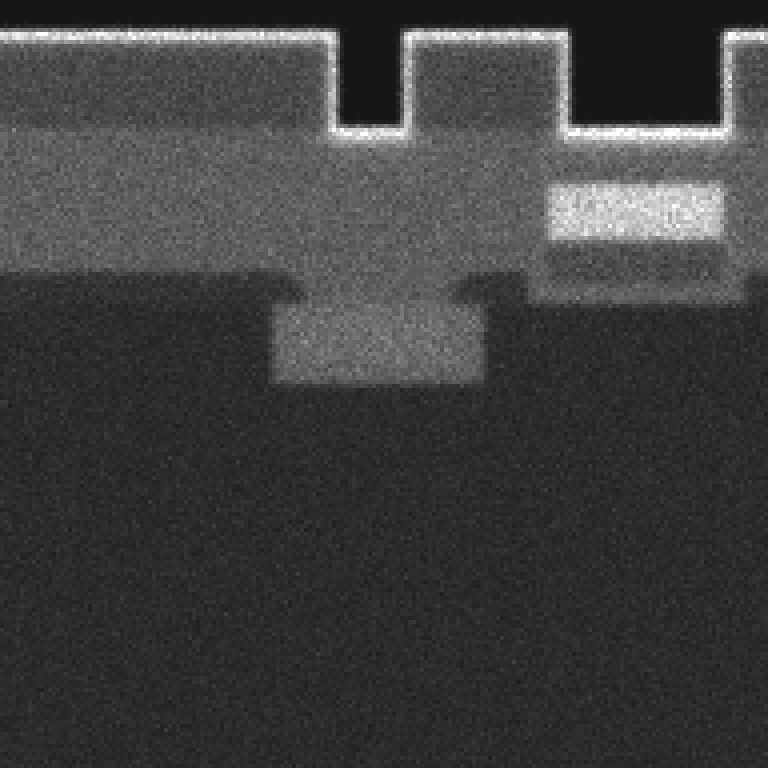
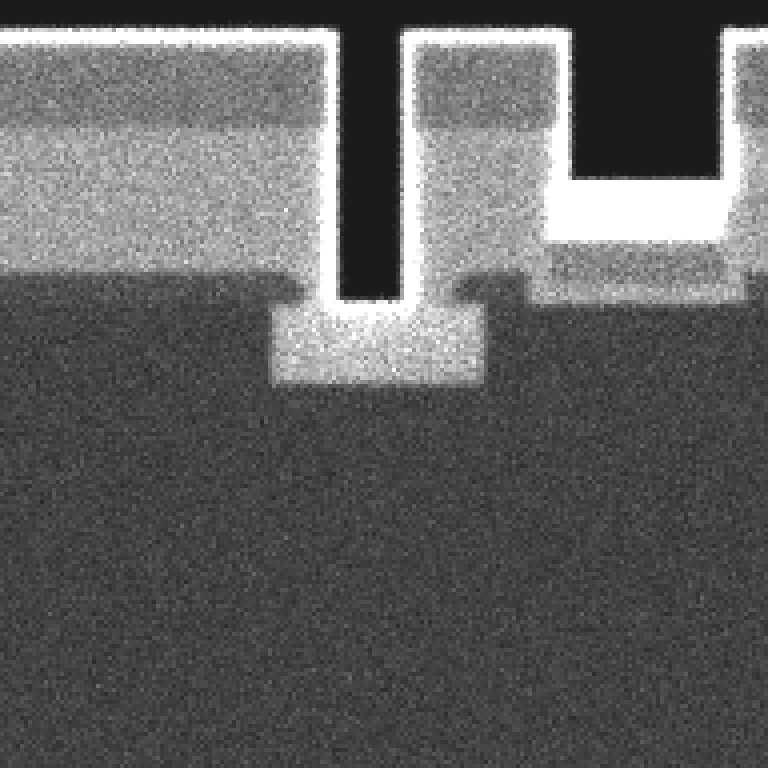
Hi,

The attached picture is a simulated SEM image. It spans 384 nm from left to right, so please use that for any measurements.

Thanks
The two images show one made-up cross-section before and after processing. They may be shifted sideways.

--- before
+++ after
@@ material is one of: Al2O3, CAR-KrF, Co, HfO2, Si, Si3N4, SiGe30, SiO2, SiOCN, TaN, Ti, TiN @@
SiO2 removed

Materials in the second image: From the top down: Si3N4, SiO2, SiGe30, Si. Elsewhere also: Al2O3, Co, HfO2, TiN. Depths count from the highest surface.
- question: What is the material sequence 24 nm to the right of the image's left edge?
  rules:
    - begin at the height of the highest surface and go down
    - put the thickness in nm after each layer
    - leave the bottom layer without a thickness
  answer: Si3N4 48, SiO2 72, SiGe30 16, Si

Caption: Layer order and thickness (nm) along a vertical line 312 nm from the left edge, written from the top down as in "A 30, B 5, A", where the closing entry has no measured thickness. empty 76, HfO2 28, TiN 22, Al2O3 10, Si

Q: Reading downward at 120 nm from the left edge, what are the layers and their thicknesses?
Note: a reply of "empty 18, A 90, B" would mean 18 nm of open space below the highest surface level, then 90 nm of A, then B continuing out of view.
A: Si3N4 48, SiO2 72, SiGe30 16, Si